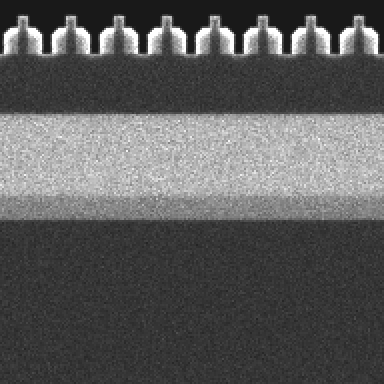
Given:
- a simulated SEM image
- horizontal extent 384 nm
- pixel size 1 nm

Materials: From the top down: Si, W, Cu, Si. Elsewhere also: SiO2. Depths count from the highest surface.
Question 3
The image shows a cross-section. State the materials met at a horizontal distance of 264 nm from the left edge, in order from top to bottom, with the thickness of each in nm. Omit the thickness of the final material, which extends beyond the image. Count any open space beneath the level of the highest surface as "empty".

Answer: Si 98, W 82, Cu 24, Si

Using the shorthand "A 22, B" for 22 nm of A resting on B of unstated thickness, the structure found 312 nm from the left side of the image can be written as Si 98, W 82, Cu 24, Si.